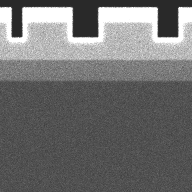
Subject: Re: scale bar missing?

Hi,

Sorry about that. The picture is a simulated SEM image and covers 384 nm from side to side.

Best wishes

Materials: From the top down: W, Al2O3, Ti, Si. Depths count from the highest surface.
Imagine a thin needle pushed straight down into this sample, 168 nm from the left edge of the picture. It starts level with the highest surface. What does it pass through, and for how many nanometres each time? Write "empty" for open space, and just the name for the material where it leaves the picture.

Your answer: empty 60, Al2O3 44, Ti 42, Si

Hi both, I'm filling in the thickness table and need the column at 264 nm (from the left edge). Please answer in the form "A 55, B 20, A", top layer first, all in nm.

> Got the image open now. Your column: W 28, Al2O3 76, Ti 42, Si